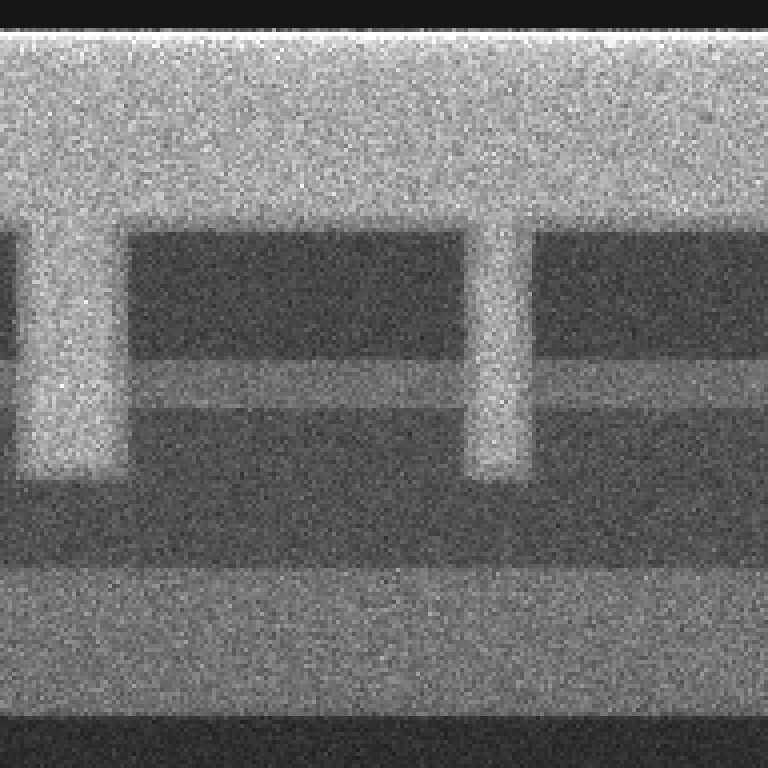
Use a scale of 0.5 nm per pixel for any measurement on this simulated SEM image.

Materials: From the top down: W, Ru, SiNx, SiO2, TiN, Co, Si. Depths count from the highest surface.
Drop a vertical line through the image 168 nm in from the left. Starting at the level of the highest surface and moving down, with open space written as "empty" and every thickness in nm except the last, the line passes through W 92, Ru 8, SiNx 64, SiO2 24, TiN 80, Co 74, Si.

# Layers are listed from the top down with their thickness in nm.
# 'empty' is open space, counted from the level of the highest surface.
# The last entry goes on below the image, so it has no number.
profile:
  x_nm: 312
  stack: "W 92, Ru 8, SiNx 64, SiO2 24, TiN 80, Co 74, Si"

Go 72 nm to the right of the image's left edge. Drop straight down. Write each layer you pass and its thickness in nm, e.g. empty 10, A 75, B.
W 92, Ru 8, SiNx 64, SiO2 24, TiN 80, Co 74, Si